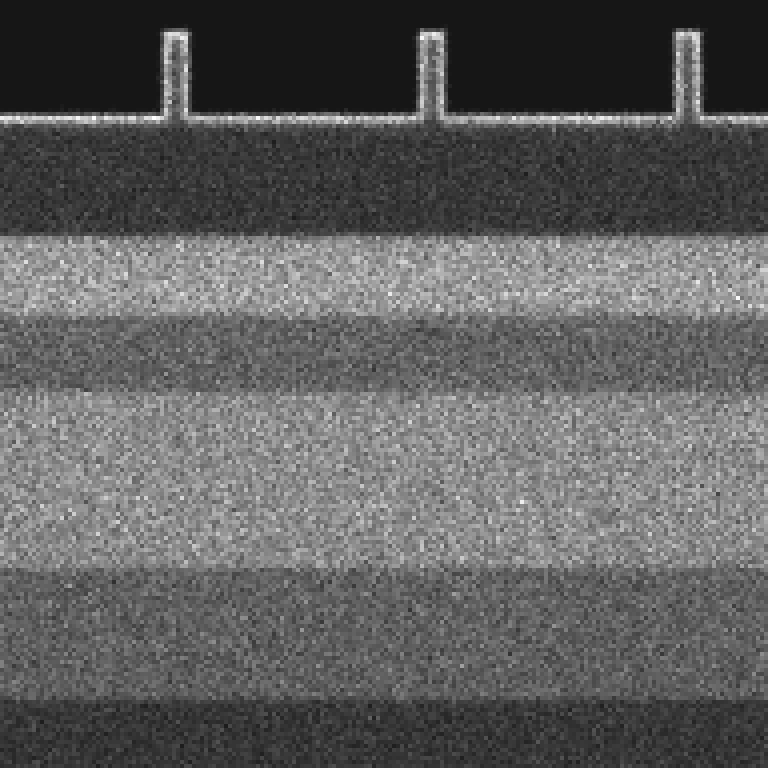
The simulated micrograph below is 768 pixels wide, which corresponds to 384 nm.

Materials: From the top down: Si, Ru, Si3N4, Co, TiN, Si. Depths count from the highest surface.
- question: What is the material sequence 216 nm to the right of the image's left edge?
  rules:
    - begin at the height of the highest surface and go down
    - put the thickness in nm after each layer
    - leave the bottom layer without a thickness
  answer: Si 102, Ru 40, Si3N4 38, Co 88, TiN 66, Si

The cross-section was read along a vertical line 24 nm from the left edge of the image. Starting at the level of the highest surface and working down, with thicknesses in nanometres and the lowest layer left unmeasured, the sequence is empty 42, Si 60, Ru 40, Si3N4 38, Co 88, TiN 66, Si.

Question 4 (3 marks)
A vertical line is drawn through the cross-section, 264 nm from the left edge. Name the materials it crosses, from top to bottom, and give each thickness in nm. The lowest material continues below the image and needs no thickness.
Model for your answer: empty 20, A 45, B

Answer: empty 42, Si 60, Ru 40, Si3N4 38, Co 88, TiN 66, Si